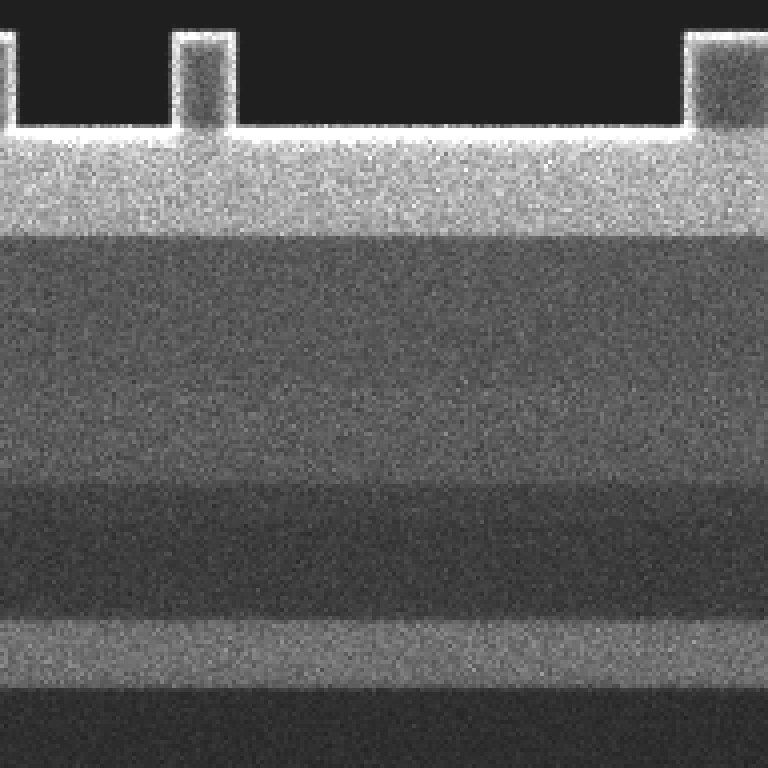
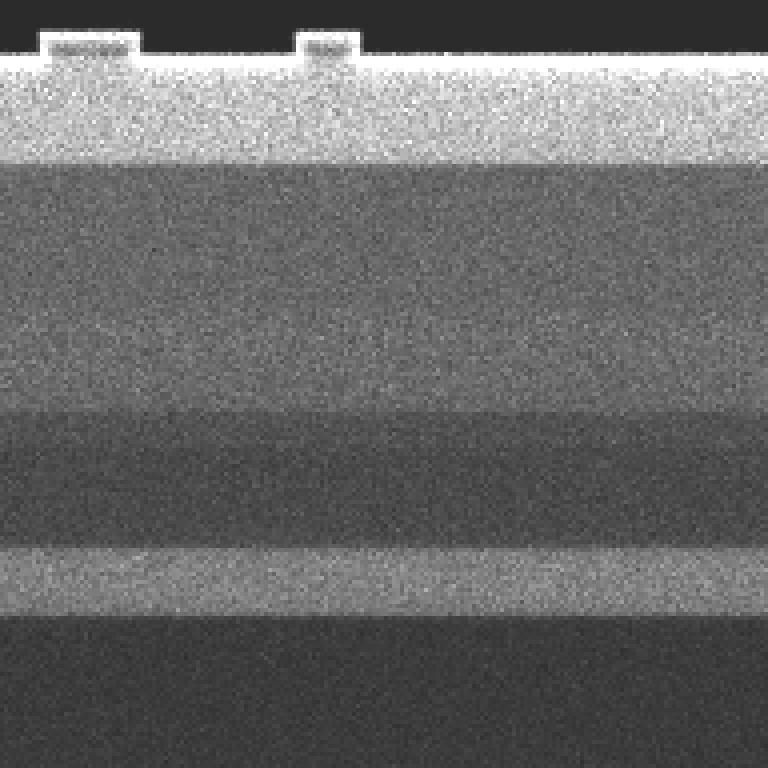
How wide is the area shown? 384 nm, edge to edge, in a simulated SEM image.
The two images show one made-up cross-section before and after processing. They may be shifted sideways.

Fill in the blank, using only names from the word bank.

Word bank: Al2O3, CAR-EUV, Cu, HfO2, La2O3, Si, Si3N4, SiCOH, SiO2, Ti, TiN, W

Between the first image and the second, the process removed SiO2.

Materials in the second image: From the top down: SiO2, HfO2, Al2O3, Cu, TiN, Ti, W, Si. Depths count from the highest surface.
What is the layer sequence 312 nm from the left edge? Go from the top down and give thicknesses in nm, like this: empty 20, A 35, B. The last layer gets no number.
empty 12, HfO2 54, Al2O3 74, Cu 50, TiN 18, Ti 50, W 34, Si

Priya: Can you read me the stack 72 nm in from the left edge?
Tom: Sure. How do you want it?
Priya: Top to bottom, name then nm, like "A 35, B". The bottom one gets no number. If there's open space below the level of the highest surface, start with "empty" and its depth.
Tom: empty 12, HfO2 54, Al2O3 74, Cu 50, TiN 18, Ti 50, W 34, Si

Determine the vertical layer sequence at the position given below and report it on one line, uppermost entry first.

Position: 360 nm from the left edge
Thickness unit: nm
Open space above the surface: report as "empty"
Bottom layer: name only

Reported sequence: empty 12, HfO2 54, Al2O3 74, Cu 50, TiN 18, Ti 50, W 34, Si